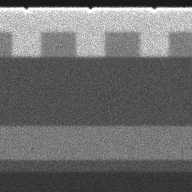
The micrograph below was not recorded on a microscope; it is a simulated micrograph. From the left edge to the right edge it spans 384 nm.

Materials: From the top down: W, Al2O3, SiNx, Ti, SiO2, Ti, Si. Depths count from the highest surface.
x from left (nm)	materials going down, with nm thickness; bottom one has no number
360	W 48, Al2O3 50, SiNx 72, Ti 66, SiO2 68, Ti 24, Si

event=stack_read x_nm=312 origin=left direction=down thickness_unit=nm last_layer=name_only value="empty 2, W 96, SiNx 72, Ti 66, SiO2 68, Ti 24, Si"